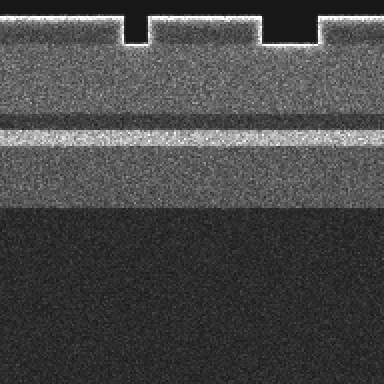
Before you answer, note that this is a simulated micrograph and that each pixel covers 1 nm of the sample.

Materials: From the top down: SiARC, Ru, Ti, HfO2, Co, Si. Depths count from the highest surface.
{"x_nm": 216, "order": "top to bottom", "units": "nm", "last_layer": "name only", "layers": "SiARC 28, Ru 70, Ti 16, HfO2 16, Co 62, Si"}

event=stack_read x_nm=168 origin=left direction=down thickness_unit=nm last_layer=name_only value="SiARC 28, Ru 70, Ti 16, HfO2 16, Co 62, Si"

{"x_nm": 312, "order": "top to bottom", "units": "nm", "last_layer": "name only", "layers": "empty 28, Ru 70, Ti 16, HfO2 16, Co 62, Si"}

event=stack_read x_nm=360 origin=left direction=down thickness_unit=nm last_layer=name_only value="SiARC 28, Ru 70, Ti 16, HfO2 16, Co 62, Si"